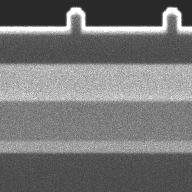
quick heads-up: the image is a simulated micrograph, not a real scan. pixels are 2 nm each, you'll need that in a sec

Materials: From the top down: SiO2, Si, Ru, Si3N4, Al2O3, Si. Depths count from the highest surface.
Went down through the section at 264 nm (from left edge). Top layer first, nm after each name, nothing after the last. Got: empty 38, SiO2 14, Si 60, Ru 74, Si3N4 80, Al2O3 24, Si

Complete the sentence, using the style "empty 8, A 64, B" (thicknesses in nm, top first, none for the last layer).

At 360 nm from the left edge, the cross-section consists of empty 10, SiO2 42, Si 60, Ru 74, Si3N4 80, Al2O3 24, Si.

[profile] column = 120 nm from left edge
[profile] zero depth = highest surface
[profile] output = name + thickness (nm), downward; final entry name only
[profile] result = empty 38, SiO2 14, Si 60, Ru 74, Si3N4 80, Al2O3 24, Si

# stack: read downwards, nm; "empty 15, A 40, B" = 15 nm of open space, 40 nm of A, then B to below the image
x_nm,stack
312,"empty 38, SiO2 14, Si 60, Ru 74, Si3N4 80, Al2O3 24, Si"